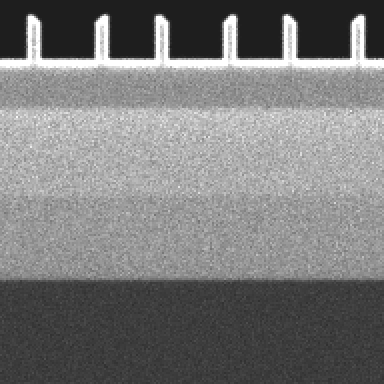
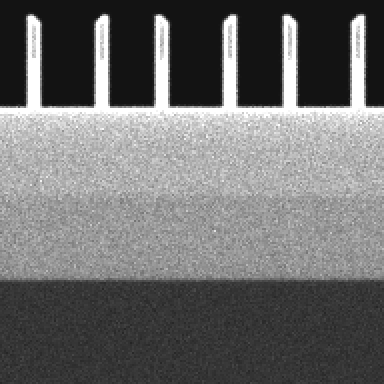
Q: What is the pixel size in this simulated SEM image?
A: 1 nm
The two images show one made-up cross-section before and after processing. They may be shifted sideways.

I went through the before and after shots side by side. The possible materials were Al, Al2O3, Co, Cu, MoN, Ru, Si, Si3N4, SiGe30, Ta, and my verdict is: removed, Al2O3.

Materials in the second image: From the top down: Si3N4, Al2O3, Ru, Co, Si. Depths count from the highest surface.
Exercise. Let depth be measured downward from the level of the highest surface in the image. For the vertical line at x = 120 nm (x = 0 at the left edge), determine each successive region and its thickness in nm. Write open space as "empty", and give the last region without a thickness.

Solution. empty 92, Ru 88, Co 84, Si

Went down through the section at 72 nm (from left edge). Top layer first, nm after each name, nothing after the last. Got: empty 92, Ru 88, Co 84, Si